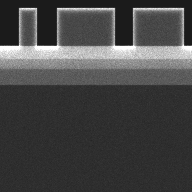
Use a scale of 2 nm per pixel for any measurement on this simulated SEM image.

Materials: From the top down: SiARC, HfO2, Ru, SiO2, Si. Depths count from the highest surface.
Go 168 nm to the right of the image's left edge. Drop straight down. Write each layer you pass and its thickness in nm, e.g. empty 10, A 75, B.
SiARC 76, HfO2 26, Ru 20, SiO2 32, Si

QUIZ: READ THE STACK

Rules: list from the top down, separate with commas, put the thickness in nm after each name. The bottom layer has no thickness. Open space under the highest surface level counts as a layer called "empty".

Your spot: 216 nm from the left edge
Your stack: SiARC 76, HfO2 26, Ru 20, SiO2 32, Si